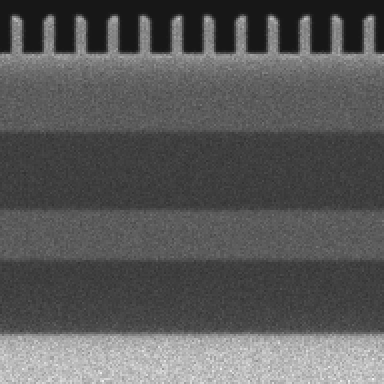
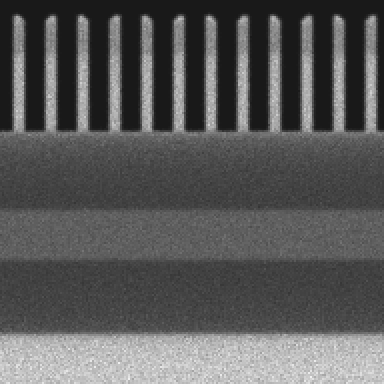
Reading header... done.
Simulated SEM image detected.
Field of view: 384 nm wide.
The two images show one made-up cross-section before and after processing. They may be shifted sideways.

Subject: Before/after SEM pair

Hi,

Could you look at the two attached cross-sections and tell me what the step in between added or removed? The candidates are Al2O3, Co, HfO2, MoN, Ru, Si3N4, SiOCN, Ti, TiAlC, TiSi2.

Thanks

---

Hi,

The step removed Co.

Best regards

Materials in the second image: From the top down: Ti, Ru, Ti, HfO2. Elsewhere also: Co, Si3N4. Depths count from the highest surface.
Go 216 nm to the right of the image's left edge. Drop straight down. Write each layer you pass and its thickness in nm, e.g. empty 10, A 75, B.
empty 116, Ti 78, Ru 50, Ti 74, HfO2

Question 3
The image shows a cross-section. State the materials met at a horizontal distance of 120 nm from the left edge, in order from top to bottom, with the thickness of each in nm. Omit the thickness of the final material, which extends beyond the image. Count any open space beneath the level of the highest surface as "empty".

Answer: empty 116, Ti 78, Ru 50, Ti 74, HfO2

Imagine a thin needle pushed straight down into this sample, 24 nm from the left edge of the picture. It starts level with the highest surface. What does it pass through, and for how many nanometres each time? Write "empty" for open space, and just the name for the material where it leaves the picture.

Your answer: empty 116, Ti 78, Ru 50, Ti 74, HfO2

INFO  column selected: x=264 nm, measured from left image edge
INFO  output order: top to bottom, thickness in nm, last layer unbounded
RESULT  empty 116, Ti 78, Ru 50, Ti 74, HfO2